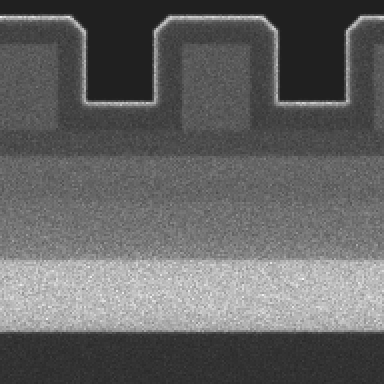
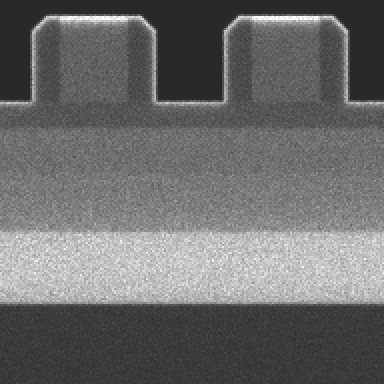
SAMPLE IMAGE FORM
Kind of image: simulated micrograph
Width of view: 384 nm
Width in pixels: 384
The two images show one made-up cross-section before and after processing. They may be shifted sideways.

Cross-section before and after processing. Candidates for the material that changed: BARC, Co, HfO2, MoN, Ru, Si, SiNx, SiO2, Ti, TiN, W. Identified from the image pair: SiNx (removed).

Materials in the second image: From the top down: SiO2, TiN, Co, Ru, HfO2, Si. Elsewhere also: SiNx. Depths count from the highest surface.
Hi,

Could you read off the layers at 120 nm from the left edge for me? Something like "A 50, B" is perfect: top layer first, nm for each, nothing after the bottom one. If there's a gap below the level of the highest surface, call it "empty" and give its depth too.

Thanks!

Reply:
SiO2 86, TiN 26, Co 46, Ru 58, HfO2 72, Si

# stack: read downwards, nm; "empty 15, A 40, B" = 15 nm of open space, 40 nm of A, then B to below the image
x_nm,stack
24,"empty 86, TiN 26, Co 46, Ru 58, HfO2 72, Si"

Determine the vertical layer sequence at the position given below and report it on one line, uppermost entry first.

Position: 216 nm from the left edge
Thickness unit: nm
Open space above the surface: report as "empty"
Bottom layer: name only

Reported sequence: empty 86, TiN 26, Co 46, Ru 58, HfO2 72, Si